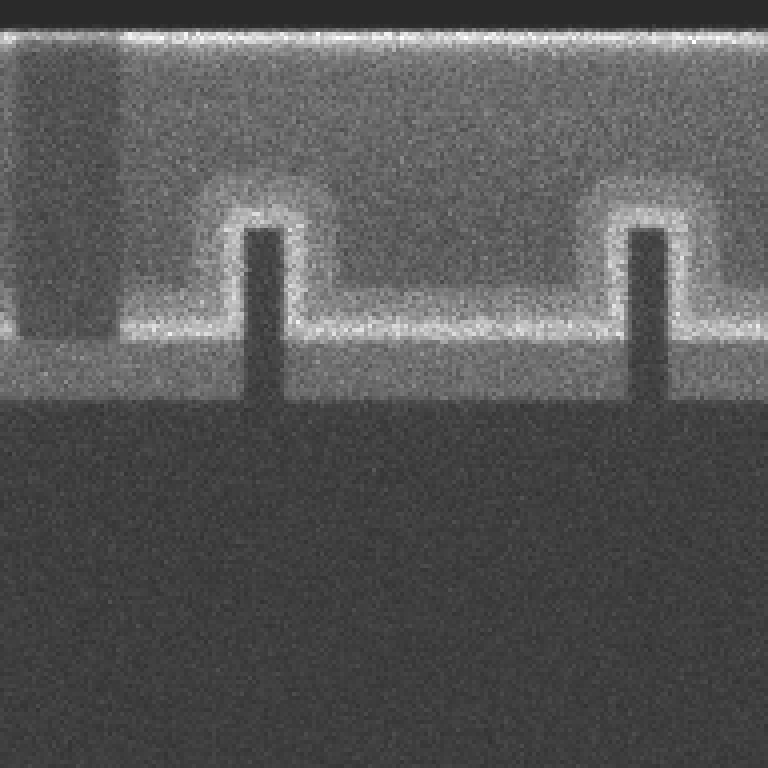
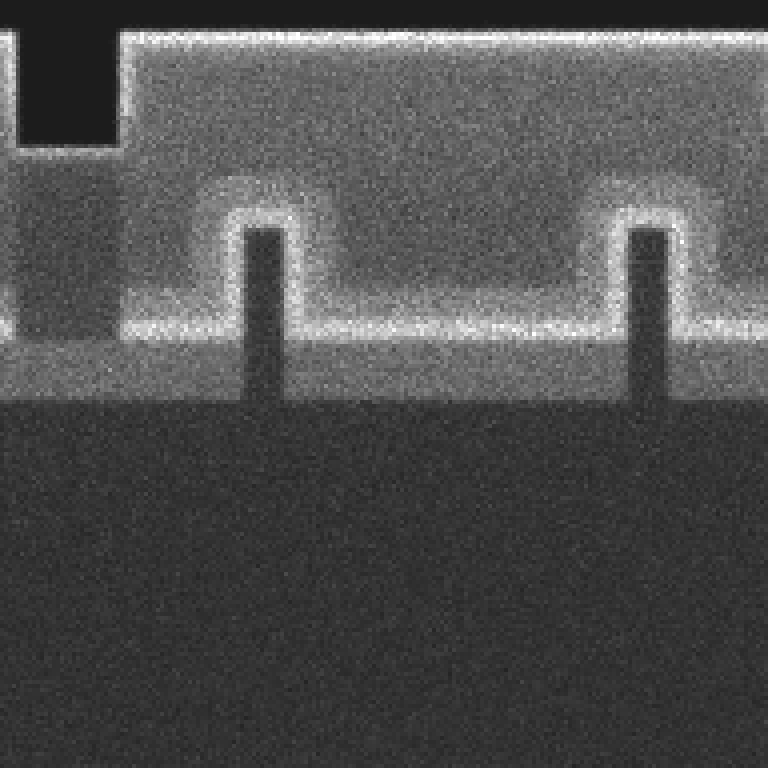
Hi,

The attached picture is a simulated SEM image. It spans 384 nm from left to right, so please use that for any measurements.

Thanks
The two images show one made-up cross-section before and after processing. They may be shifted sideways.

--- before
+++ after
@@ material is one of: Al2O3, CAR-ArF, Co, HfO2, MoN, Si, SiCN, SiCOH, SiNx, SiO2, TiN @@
SiNx removed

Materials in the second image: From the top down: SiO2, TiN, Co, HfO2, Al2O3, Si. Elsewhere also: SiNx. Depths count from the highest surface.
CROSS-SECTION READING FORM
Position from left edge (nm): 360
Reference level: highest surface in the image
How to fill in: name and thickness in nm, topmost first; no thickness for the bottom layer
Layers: SiO2 42, TiN 86, Co 16, HfO2 10, Al2O3 30, Si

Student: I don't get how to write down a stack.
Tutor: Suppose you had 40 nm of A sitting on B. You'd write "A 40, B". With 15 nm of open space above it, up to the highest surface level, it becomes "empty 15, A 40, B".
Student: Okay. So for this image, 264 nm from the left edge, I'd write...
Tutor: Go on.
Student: SiO2 42, TiN 86, Co 16, HfO2 10, Al2O3 30, Si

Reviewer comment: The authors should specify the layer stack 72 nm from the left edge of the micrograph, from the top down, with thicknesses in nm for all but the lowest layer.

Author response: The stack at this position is SiO2 42, TiN 86, Co 16, HfO2 10, Al2O3 30, Si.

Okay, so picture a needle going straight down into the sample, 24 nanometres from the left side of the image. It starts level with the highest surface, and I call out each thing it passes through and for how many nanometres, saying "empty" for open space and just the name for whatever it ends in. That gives empty 58, SiNx 96, Al2O3 30, Si